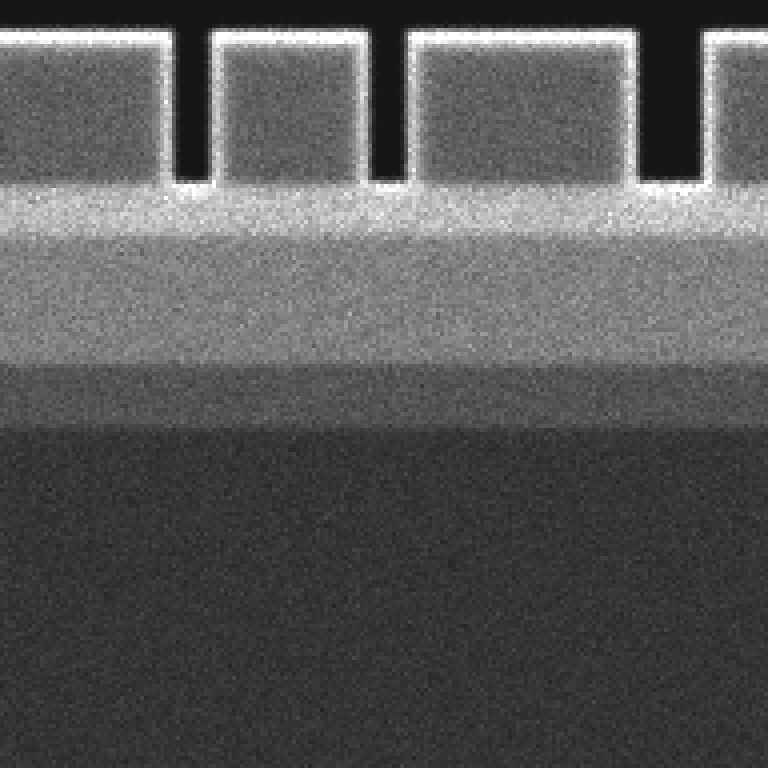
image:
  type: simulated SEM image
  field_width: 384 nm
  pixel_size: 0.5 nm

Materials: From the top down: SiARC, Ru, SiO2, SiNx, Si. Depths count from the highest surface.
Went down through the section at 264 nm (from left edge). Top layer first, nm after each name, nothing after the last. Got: SiARC 76, Ru 26, SiO2 64, SiNx 32, Si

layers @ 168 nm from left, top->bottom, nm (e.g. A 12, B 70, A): SiARC 76, Ru 26, SiO2 64, SiNx 32, Si